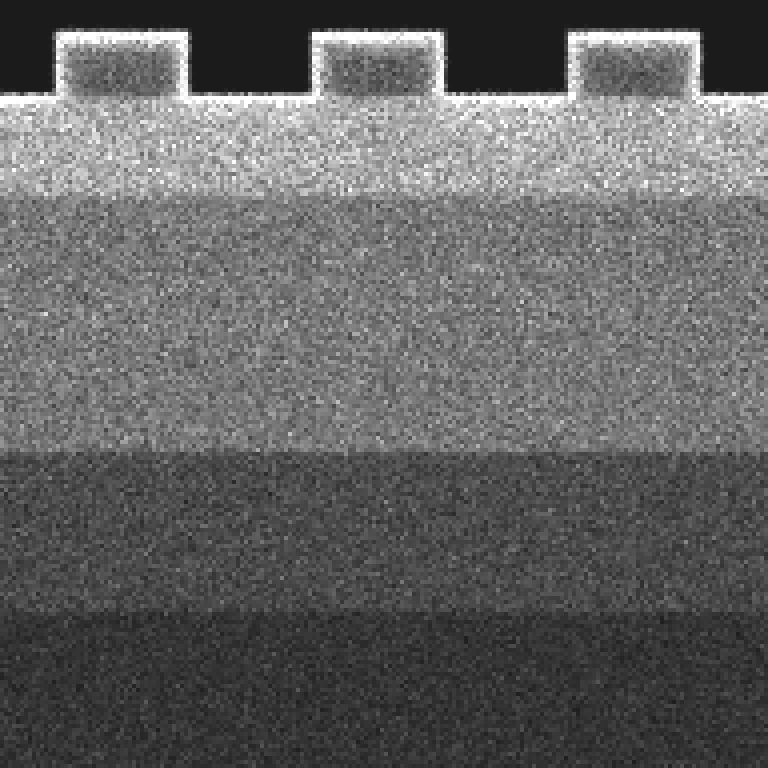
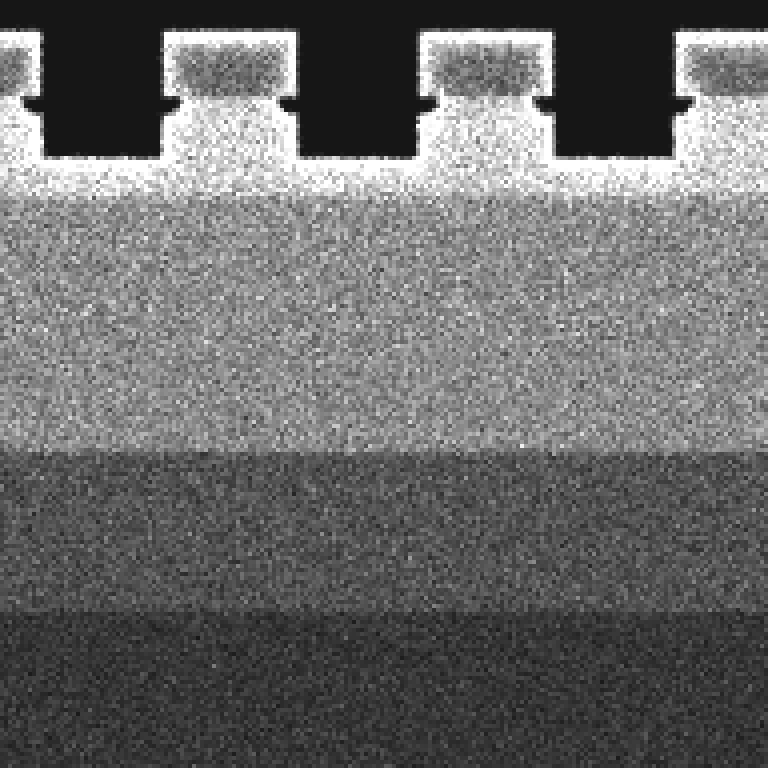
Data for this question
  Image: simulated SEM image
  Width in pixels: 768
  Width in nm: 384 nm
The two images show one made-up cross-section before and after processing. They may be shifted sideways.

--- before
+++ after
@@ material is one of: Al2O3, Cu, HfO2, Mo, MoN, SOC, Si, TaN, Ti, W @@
W removed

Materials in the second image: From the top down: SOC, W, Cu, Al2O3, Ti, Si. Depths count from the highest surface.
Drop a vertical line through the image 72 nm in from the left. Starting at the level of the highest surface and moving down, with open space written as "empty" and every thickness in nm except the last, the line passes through empty 64, W 18, Cu 72, Al2O3 56, Ti 80, Si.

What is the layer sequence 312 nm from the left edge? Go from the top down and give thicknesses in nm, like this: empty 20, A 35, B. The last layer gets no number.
empty 64, W 18, Cu 72, Al2O3 56, Ti 80, Si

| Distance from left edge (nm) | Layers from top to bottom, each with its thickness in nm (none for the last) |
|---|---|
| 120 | SOC 32, W 50, Cu 72, Al2O3 56, Ti 80, Si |